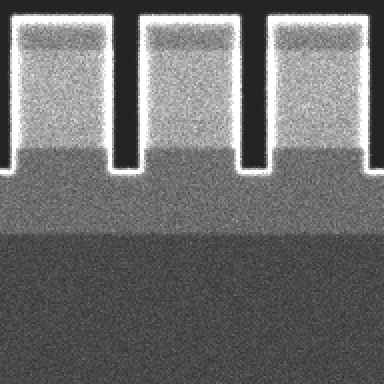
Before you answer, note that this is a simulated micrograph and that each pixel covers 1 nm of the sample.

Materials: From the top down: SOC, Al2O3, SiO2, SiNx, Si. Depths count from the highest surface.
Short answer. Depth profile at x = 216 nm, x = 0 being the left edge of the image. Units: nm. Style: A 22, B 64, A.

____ SOC 34, Al2O3 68, SiO2 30, SiNx 86, Si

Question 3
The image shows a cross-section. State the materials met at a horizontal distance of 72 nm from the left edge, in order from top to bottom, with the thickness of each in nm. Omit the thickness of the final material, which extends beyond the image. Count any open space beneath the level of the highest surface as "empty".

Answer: SOC 34, Al2O3 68, SiO2 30, SiNx 86, Si